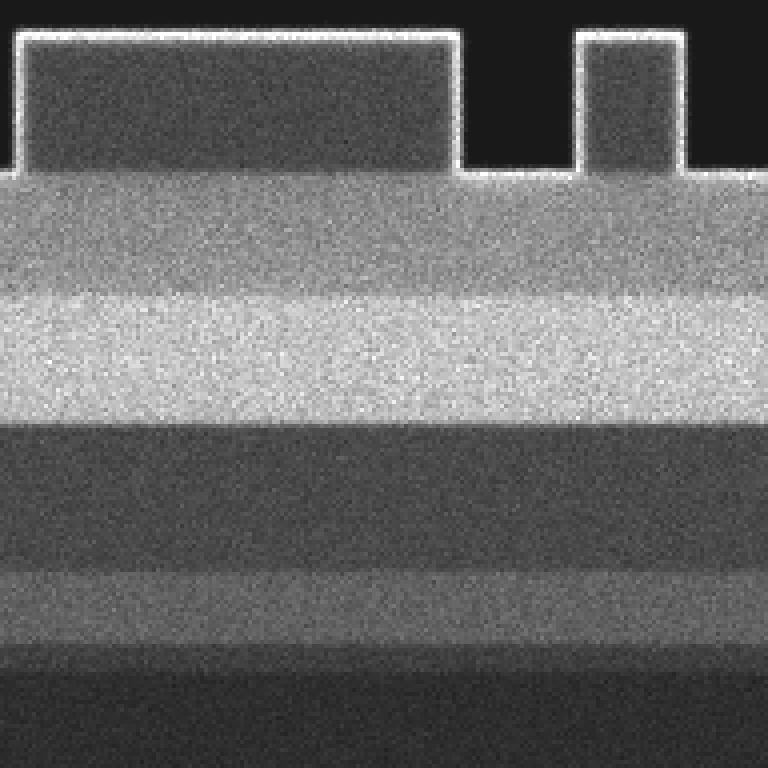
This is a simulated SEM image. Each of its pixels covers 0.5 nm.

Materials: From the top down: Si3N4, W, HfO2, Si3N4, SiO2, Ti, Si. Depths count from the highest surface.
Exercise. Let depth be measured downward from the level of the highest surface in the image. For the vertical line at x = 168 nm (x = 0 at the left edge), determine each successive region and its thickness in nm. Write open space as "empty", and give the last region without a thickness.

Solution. Si3N4 70, W 62, HfO2 64, Si3N4 74, SiO2 36, Ti 14, Si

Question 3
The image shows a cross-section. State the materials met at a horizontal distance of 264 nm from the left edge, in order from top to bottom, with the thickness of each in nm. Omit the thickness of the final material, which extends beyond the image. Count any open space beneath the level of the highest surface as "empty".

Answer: empty 70, W 62, HfO2 64, Si3N4 74, SiO2 36, Ti 14, Si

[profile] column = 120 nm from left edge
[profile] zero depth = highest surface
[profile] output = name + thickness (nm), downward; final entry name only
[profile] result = Si3N4 70, W 62, HfO2 64, Si3N4 74, SiO2 36, Ti 14, Si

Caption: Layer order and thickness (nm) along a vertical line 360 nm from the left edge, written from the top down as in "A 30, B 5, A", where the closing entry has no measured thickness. empty 70, W 62, HfO2 64, Si3N4 74, SiO2 36, Ti 14, Si